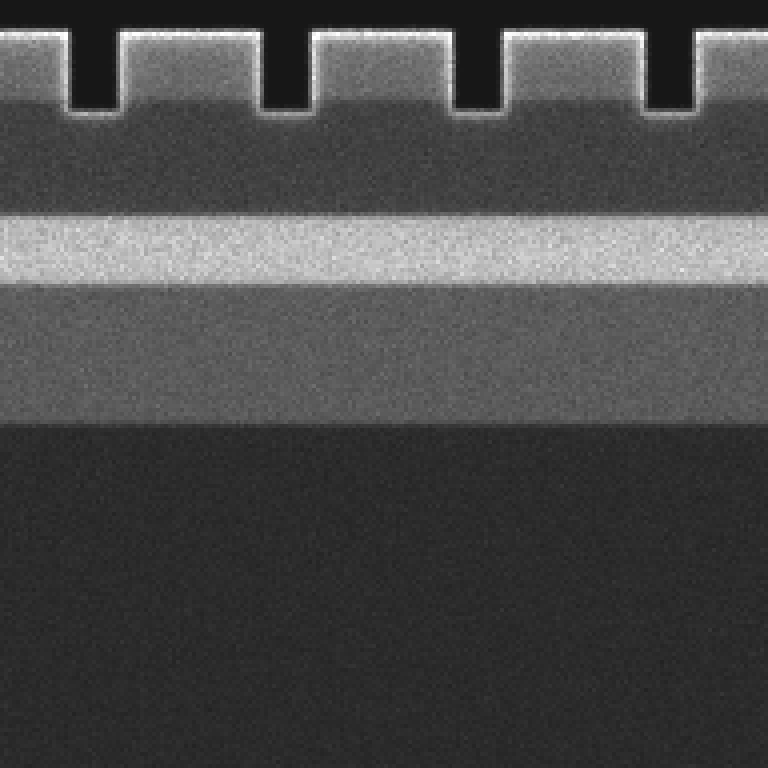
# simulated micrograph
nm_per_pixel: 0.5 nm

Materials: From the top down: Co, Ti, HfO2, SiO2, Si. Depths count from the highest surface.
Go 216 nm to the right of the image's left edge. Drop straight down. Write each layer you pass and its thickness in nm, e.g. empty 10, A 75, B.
Co 34, Ti 58, HfO2 34, SiO2 70, Si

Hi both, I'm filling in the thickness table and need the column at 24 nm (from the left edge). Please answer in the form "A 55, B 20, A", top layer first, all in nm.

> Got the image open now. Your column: Co 34, Ti 58, HfO2 34, SiO2 70, Si